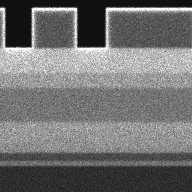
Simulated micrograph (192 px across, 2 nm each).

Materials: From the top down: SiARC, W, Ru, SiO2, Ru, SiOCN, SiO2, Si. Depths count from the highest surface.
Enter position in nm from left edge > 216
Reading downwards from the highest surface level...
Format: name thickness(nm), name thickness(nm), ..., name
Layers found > SiARC 80, W 50, Ru 30, SiO2 68, Ru 62, SiOCN 16, SiO2 10, Si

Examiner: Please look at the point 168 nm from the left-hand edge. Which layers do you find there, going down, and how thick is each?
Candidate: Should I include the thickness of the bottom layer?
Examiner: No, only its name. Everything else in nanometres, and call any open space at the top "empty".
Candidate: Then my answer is empty 80, W 50, Ru 30, SiO2 68, Ru 62, SiOCN 16, SiO2 10, Si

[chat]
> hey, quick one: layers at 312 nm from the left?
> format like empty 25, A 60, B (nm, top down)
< SiARC 80, W 50, Ru 30, SiO2 68, Ru 62, SiOCN 16, SiO2 10, Si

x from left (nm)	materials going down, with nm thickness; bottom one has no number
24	empty 80, W 50, Ru 30, SiO2 68, Ru 62, SiOCN 16, SiO2 10, Si